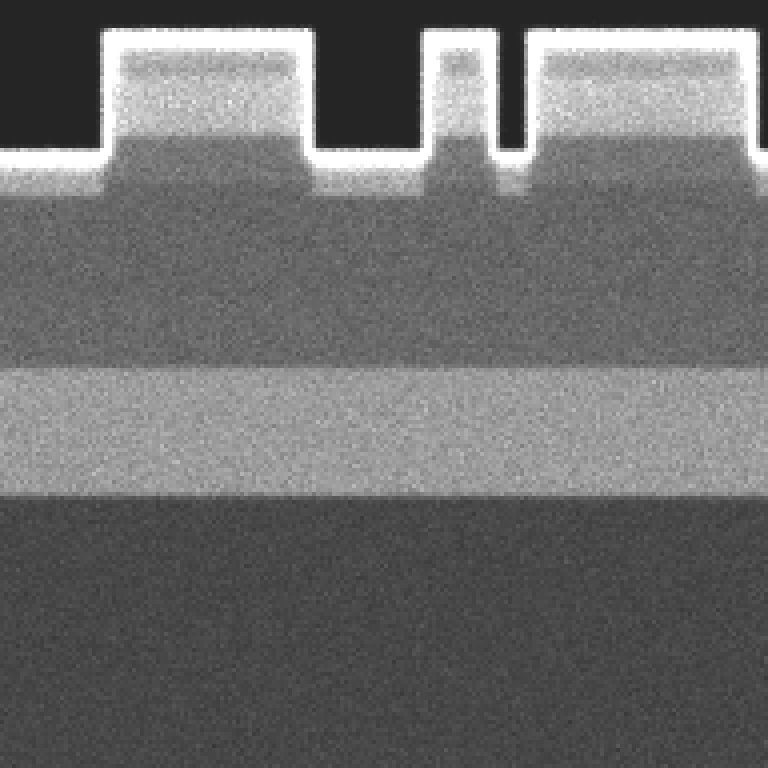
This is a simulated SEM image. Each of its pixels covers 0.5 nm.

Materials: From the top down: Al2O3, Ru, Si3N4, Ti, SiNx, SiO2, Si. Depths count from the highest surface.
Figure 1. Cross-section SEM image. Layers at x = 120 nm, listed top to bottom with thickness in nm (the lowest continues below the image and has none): Al2O3 22, Ru 30, Si3N4 24, Ti 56, SiNx 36, SiO2 64, Si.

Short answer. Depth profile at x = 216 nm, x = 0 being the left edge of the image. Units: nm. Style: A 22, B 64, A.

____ Al2O3 22, Ru 30, Si3N4 24, Ti 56, SiNx 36, SiO2 64, Si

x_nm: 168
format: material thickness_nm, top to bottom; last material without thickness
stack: empty 60, Al2O3 22, Ti 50, SiNx 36, SiO2 64, Si